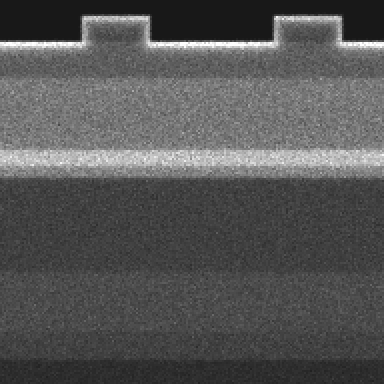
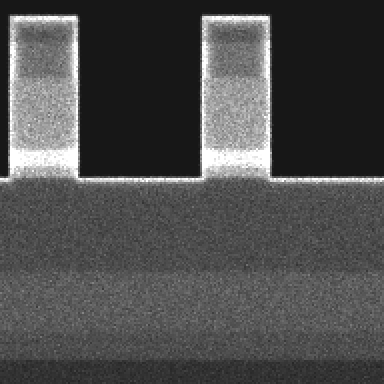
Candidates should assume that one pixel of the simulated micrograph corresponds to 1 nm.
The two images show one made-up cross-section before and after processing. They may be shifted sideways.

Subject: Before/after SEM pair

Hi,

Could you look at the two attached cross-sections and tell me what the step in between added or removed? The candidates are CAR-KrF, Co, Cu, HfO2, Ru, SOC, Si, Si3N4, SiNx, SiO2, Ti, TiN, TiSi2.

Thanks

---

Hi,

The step removed Co and HfO2 and Ru and SiO2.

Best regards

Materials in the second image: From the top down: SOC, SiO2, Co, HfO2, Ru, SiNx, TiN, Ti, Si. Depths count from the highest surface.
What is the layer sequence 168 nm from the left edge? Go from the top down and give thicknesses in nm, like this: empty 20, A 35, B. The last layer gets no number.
empty 162, SiNx 94, TiN 60, Ti 28, Si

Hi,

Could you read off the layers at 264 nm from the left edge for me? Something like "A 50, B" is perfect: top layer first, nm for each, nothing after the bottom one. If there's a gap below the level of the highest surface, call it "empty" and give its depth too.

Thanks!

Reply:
SOC 26, SiO2 36, Co 72, HfO2 16, Ru 12, SiNx 94, TiN 60, Ti 28, Si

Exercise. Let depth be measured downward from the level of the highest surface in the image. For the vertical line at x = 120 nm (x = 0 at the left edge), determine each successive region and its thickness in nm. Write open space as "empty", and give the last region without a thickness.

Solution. empty 162, SiNx 94, TiN 60, Ti 28, Si